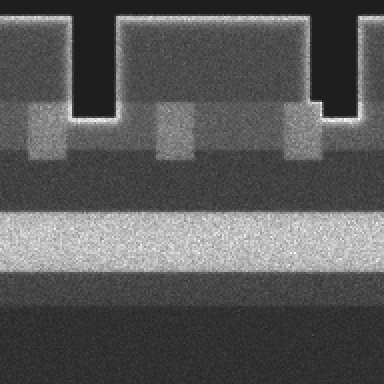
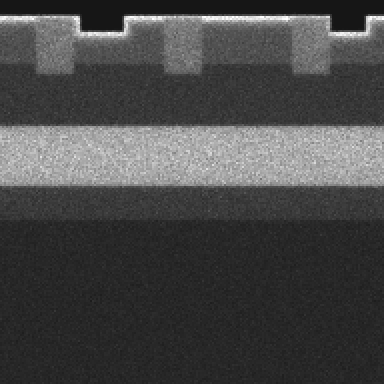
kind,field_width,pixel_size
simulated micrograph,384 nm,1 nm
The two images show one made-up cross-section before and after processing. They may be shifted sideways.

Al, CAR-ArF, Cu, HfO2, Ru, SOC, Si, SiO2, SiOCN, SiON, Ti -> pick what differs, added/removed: SOC removed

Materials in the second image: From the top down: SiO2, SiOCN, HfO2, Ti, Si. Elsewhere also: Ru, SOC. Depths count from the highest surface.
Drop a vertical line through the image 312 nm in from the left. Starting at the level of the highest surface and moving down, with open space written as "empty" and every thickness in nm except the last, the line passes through Ru 58, SiOCN 52, HfO2 60, Ti 34, Si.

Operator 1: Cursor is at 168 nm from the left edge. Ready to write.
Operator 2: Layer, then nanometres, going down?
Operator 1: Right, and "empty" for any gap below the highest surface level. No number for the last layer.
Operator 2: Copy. Ru 58, SiOCN 52, HfO2 60, Ti 34, Si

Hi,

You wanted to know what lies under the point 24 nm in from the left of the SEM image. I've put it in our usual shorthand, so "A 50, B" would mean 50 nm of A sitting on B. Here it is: SiO2 48, SiOCN 62, HfO2 60, Ti 34, Si